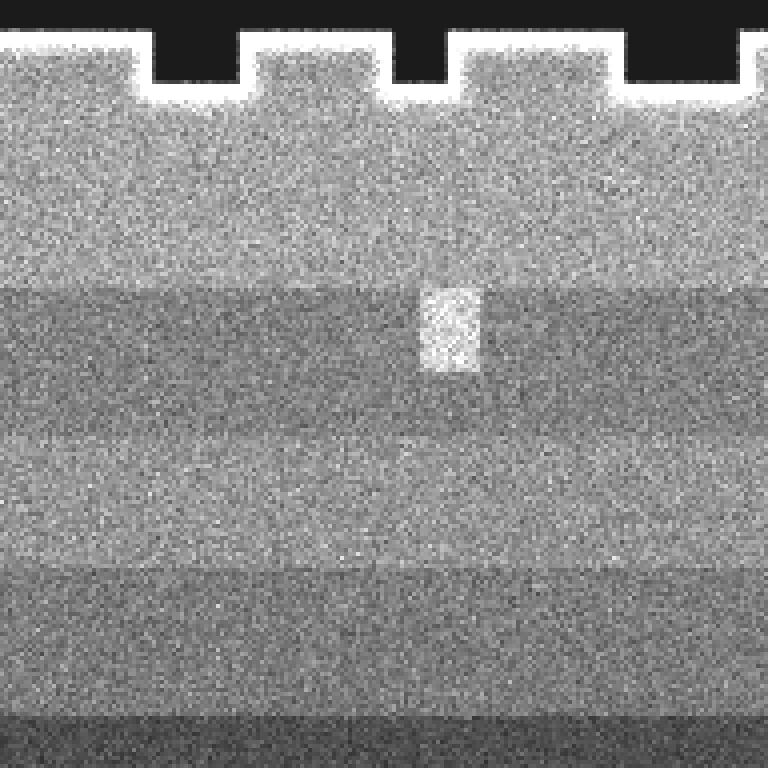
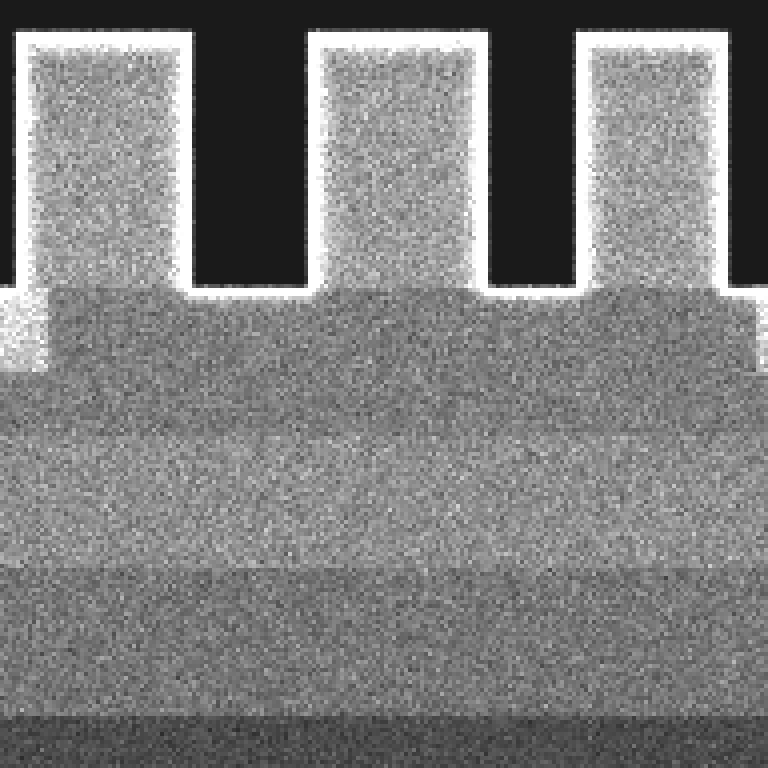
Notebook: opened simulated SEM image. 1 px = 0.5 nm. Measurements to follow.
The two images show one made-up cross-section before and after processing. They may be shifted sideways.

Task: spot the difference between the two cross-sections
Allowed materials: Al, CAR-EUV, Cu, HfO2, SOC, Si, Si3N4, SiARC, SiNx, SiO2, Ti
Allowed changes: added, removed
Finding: removed SOC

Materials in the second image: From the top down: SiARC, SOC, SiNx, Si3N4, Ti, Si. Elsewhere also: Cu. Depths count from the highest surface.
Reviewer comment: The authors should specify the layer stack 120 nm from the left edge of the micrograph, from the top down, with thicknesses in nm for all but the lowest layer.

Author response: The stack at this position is empty 128, SiNx 74, Si3N4 66, Ti 74, Si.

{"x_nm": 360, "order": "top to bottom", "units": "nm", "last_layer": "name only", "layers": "SiARC 26, SOC 102, SiNx 74, Si3N4 66, Ti 74, Si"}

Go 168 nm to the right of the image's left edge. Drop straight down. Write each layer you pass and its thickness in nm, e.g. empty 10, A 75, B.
SiARC 26, SOC 102, SiNx 74, Si3N4 66, Ti 74, Si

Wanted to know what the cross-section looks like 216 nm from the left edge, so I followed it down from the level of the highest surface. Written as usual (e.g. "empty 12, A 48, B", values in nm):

SiARC 26, SOC 102, SiNx 74, Si3N4 66, Ti 74, Si